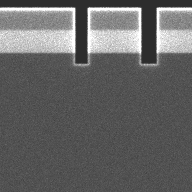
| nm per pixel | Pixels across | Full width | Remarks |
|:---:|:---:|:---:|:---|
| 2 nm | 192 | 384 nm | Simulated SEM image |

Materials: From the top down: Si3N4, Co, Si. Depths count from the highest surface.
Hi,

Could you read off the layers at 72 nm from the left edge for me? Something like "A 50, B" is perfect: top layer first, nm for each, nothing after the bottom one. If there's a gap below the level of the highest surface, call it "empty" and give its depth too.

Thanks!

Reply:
Si3N4 44, Co 46, Si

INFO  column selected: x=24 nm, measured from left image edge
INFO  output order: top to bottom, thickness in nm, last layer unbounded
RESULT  Si3N4 44, Co 46, Si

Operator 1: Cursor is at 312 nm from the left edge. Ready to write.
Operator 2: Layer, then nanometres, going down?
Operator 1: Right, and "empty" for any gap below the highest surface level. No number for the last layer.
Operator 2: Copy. empty 112, Si